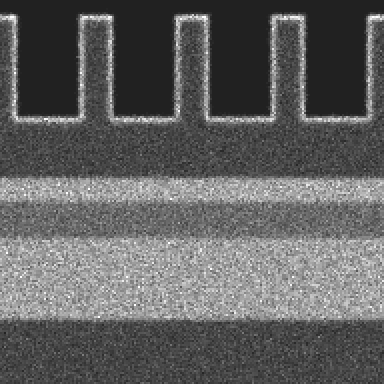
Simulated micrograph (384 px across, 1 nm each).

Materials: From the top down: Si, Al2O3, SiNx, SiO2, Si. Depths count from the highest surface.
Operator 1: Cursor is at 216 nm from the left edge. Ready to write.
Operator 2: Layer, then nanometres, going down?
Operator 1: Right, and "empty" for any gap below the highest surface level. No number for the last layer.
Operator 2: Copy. empty 102, Si 60, Al2O3 24, SiNx 36, SiO2 82, Si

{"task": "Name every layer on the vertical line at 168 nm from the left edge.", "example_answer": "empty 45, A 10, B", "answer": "empty 102, Si 60, Al2O3 24, SiNx 36, SiO2 82, Si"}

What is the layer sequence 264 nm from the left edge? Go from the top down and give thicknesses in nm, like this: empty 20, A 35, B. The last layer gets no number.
empty 102, Si 60, Al2O3 24, SiNx 36, SiO2 82, Si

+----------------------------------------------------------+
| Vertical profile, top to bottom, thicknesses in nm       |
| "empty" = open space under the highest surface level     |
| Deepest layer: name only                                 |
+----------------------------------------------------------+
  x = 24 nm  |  empty 102, Si 60, Al2O3 24, SiNx 36, SiO2 82, Si